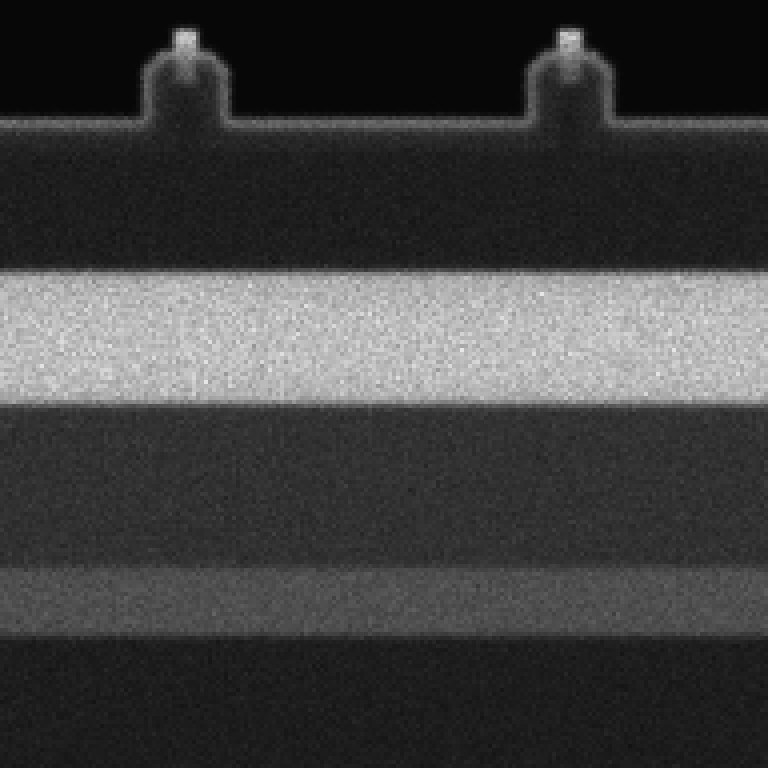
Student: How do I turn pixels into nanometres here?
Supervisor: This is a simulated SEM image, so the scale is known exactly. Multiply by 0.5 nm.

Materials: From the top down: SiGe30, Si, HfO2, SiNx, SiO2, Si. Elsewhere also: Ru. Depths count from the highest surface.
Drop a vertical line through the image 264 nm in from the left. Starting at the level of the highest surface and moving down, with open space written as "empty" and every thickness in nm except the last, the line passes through empty 18, SiGe30 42, Si 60, HfO2 66, SiNx 82, SiO2 34, Si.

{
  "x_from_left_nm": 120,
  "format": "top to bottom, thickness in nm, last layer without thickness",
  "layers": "empty 44, SiGe30 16, Si 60, HfO2 66, SiNx 82, SiO2 34, Si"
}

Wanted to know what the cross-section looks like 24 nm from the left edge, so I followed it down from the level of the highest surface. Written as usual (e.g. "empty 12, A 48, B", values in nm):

empty 44, SiGe30 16, Si 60, HfO2 66, SiNx 82, SiO2 34, Si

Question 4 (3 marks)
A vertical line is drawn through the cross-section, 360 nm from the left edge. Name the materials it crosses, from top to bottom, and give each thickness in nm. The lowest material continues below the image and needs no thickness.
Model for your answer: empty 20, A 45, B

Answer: empty 44, SiGe30 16, Si 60, HfO2 66, SiNx 82, SiO2 34, Si